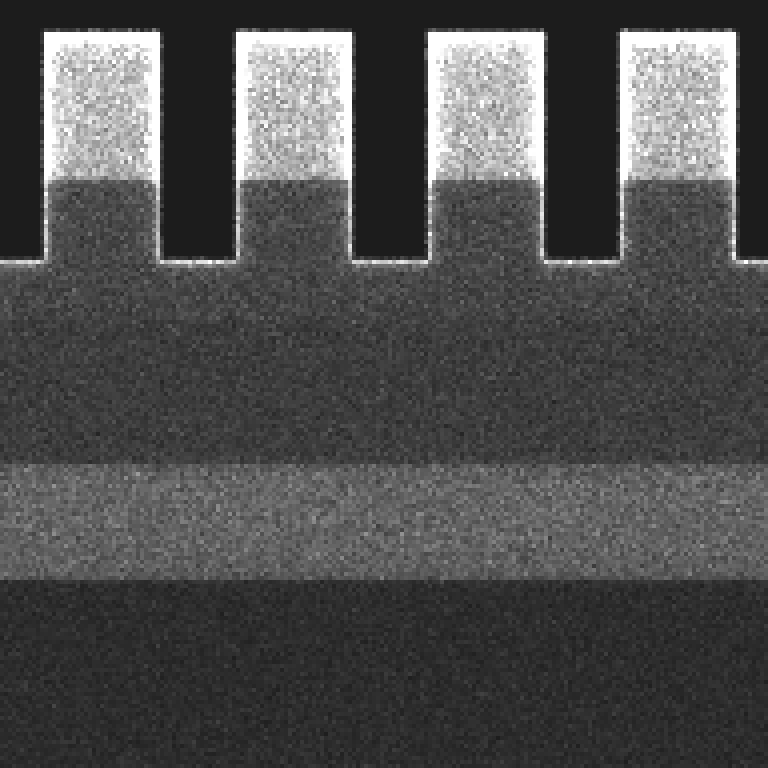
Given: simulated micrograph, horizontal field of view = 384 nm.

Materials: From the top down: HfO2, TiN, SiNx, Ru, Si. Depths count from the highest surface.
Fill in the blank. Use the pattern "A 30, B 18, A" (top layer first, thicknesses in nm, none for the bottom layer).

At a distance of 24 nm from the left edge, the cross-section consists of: HfO2 74, TiN 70, SiNx 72, Ru 58, Si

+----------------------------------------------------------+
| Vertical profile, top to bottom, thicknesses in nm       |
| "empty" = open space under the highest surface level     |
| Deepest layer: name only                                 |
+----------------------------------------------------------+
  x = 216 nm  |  HfO2 74, TiN 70, SiNx 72, Ru 58, Si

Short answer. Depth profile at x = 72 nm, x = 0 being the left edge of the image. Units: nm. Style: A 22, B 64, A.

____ HfO2 74, TiN 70, SiNx 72, Ru 58, Si